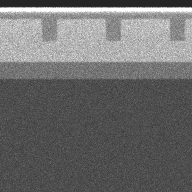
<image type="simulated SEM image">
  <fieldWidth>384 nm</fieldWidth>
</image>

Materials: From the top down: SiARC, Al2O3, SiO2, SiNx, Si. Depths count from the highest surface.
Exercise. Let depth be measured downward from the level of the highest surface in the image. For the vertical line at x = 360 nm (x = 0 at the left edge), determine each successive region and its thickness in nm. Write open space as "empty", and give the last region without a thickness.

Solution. SiARC 66, SiO2 42, SiNx 34, Si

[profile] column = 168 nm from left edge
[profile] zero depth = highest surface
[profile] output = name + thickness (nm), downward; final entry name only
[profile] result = SiARC 22, Al2O3 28, SiO2 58, SiNx 34, Si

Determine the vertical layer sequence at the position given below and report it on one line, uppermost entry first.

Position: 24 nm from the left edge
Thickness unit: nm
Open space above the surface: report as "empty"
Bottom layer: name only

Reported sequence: SiARC 22, Al2O3 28, SiO2 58, SiNx 34, Si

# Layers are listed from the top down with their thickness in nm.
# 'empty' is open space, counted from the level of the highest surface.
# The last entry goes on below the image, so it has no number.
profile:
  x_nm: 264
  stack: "SiARC 22, Al2O3 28, SiO2 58, SiNx 34, Si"